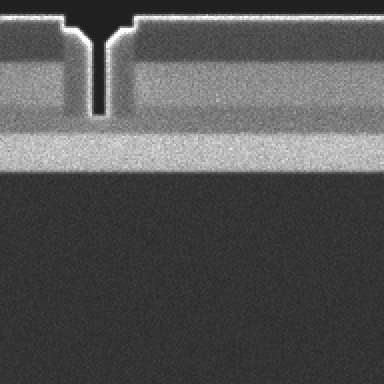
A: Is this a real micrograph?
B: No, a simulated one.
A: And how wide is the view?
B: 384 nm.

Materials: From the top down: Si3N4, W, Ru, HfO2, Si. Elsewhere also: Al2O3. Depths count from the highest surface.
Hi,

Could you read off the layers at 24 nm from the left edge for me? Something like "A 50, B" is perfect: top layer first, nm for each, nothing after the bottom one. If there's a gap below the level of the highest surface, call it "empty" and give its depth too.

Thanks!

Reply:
Si3N4 46, W 44, Ru 28, HfO2 38, Si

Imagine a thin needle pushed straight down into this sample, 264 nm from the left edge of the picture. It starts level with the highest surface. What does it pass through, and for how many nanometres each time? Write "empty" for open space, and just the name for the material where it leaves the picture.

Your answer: Si3N4 46, W 44, Ru 28, HfO2 38, Si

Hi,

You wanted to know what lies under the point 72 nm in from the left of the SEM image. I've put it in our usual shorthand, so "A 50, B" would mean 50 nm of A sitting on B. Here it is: empty 12, Al2O3 88, Ru 18, HfO2 38, Si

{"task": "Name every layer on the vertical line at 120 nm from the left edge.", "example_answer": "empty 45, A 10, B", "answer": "empty 12, Al2O3 88, Ru 18, HfO2 38, Si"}